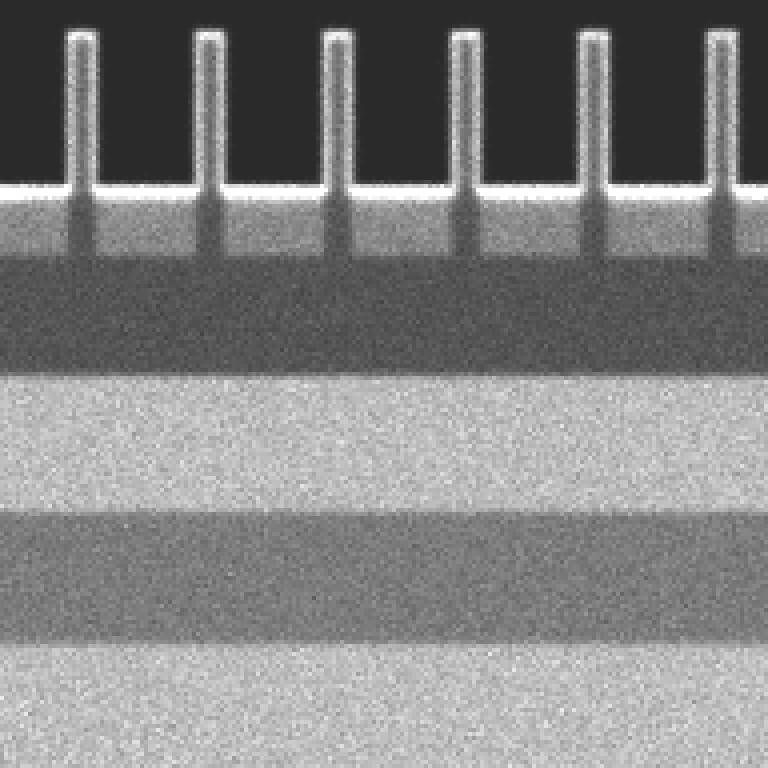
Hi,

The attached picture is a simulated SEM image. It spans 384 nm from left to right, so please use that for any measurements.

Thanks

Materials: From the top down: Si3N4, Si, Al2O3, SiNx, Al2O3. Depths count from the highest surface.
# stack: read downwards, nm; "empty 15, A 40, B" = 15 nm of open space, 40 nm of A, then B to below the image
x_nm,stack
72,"empty 78, Si3N4 34, Si 60, Al2O3 68, SiNx 66, Al2O3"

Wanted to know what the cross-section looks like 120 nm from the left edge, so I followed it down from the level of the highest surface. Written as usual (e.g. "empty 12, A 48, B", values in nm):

empty 78, Si3N4 34, Si 60, Al2O3 68, SiNx 66, Al2O3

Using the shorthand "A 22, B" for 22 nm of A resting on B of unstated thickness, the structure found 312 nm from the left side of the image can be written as empty 78, Si3N4 34, Si 60, Al2O3 68, SiNx 66, Al2O3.